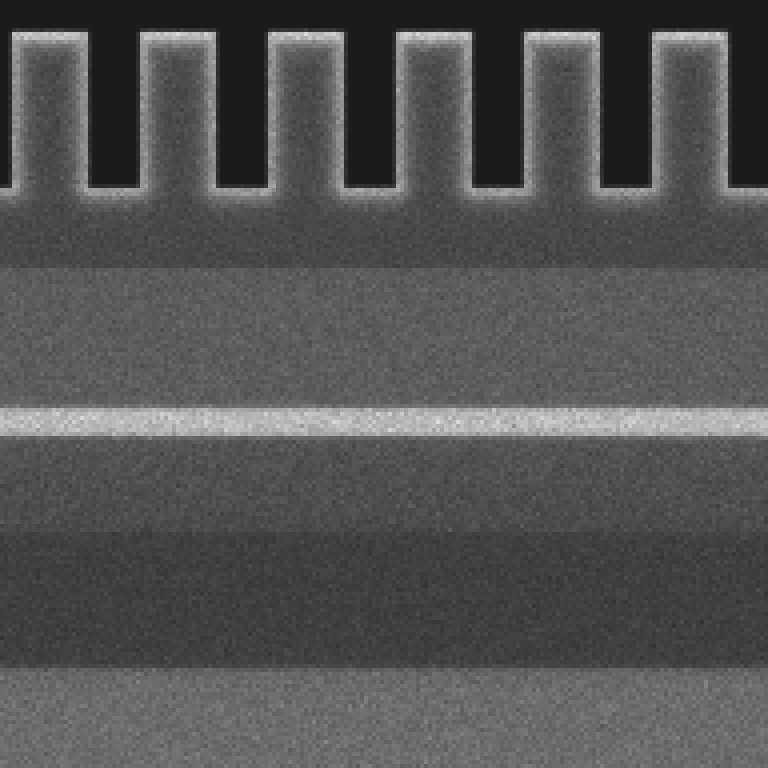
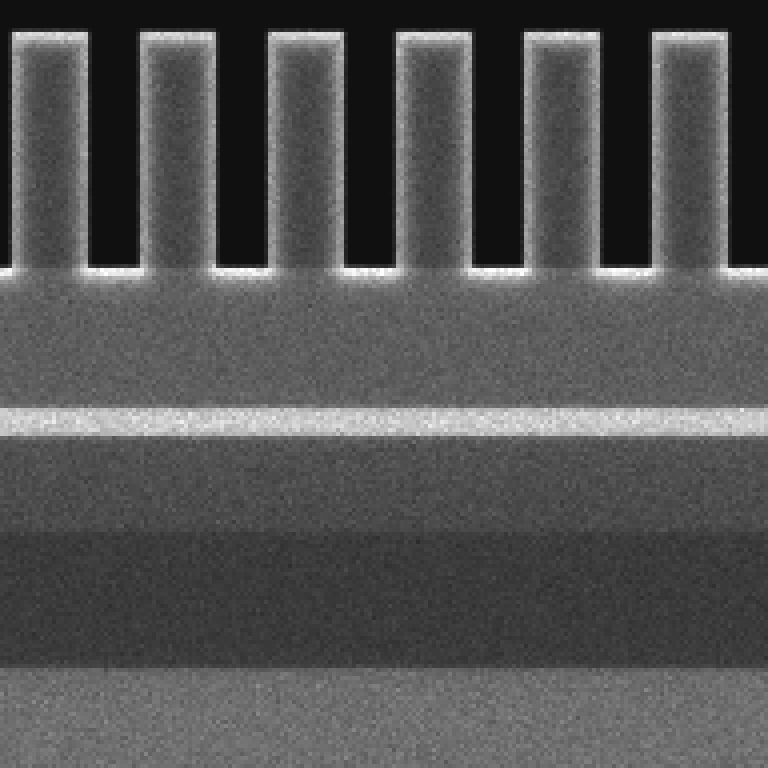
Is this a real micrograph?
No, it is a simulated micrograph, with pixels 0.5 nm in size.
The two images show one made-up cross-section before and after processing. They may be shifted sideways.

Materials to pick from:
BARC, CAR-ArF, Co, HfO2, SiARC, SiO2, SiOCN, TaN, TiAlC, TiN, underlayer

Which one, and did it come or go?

underlayer - removed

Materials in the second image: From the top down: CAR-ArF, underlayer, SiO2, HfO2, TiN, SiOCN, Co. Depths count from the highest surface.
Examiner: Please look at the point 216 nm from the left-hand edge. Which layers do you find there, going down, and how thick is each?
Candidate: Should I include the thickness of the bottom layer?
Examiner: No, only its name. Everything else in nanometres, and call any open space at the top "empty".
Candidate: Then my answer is CAR-ArF 78, underlayer 40, SiO2 70, HfO2 14, TiN 48, SiOCN 68, Co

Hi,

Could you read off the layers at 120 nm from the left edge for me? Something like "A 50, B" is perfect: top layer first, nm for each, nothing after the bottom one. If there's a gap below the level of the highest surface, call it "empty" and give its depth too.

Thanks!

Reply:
empty 118, SiO2 70, HfO2 14, TiN 48, SiOCN 68, Co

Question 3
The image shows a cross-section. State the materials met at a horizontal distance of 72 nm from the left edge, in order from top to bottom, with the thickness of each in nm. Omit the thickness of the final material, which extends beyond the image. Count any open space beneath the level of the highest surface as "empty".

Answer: CAR-ArF 78, underlayer 40, SiO2 70, HfO2 14, TiN 48, SiOCN 68, Co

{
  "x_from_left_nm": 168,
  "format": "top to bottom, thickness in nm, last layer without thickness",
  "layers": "CAR-ArF 78, underlayer 40, SiO2 70, HfO2 14, TiN 48, SiOCN 68, Co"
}